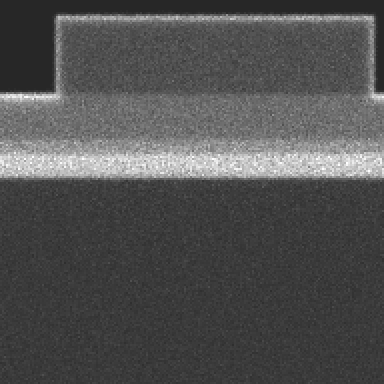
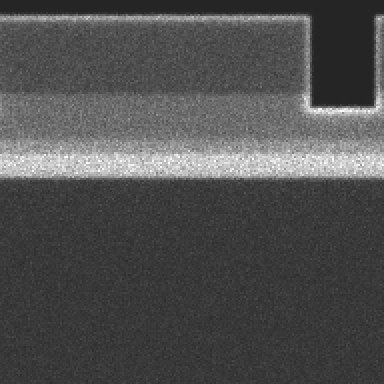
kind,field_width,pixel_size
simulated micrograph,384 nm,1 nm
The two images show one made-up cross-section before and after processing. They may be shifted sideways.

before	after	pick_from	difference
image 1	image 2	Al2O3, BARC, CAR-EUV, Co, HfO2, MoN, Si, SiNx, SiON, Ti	Al2O3 removed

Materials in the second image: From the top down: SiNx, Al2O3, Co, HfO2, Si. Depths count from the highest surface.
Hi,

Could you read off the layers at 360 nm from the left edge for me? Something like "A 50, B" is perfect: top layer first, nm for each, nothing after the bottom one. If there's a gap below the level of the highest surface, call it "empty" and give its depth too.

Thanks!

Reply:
empty 92, Al2O3 32, Co 14, HfO2 24, Si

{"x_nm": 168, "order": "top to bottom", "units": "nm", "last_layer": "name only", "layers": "SiNx 78, Al2O3 46, Co 14, HfO2 24, Si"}